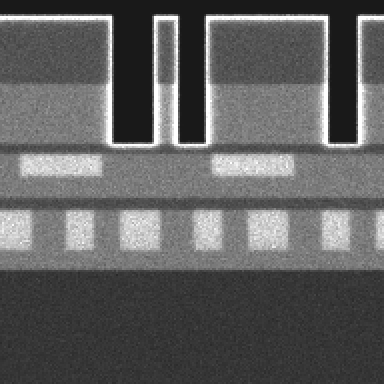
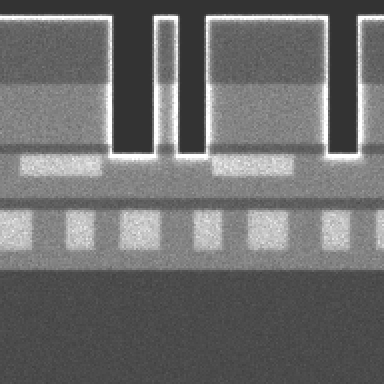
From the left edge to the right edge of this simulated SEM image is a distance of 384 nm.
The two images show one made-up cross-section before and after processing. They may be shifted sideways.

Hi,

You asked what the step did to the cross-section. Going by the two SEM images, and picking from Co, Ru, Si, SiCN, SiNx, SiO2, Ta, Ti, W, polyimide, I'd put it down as SiCN, removed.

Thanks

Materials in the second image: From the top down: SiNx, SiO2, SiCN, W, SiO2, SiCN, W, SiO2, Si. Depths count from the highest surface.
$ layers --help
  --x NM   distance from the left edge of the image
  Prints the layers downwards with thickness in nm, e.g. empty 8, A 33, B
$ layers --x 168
SiNx 68, SiO2 60, SiCN 10, SiO2 44, SiCN 12, SiO2 60, Si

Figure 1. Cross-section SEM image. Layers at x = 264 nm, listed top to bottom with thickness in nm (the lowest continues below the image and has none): SiNx 68, SiO2 60, SiCN 10, W 22, SiO2 22, SiCN 12, W 40, SiO2 20, Si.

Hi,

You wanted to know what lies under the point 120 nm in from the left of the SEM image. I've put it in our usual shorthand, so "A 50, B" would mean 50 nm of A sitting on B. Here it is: empty 138, SiO2 44, SiCN 12, W 40, SiO2 20, Si